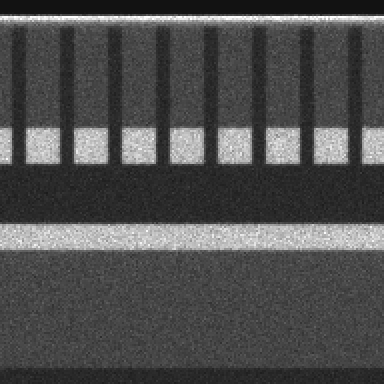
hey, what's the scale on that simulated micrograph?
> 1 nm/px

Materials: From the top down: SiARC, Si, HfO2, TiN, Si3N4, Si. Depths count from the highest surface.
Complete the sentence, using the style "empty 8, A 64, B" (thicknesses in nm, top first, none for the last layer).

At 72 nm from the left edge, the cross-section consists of SiARC 10, Si 198, HfO2 26, TiN 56, Si3N4 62, Si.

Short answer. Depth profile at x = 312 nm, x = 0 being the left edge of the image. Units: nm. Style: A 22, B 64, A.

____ SiARC 10, Si 198, HfO2 26, TiN 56, Si3N4 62, Si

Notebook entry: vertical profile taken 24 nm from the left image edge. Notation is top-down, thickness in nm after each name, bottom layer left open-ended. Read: SiARC 10, Si 198, HfO2 26, TiN 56, Si3N4 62, Si